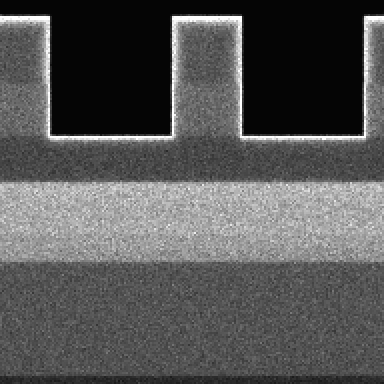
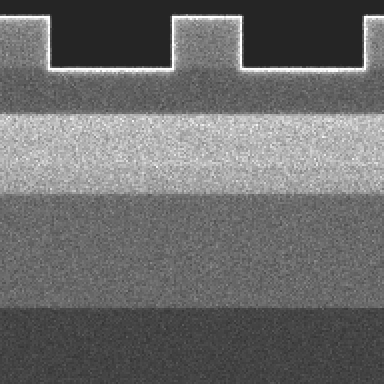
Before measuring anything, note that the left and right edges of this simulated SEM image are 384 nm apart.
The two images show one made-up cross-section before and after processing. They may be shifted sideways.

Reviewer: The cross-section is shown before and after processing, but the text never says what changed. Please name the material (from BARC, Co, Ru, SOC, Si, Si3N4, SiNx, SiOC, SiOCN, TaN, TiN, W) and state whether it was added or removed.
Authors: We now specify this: SOC, removed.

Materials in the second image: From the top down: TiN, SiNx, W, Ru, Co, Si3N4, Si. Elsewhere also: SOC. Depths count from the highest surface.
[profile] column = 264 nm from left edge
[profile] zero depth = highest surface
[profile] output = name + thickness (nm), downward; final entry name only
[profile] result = empty 52, SiNx 46, W 52, Ru 14, Co 14, Si3N4 114, Si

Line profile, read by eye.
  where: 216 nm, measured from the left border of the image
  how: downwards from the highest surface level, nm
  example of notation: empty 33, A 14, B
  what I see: TiN 52, SiNx 46, W 52, Ru 14, Co 14, Si3N4 114, Si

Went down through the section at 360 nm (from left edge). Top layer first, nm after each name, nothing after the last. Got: empty 52, SiNx 46, W 52, Ru 14, Co 14, Si3N4 114, Si